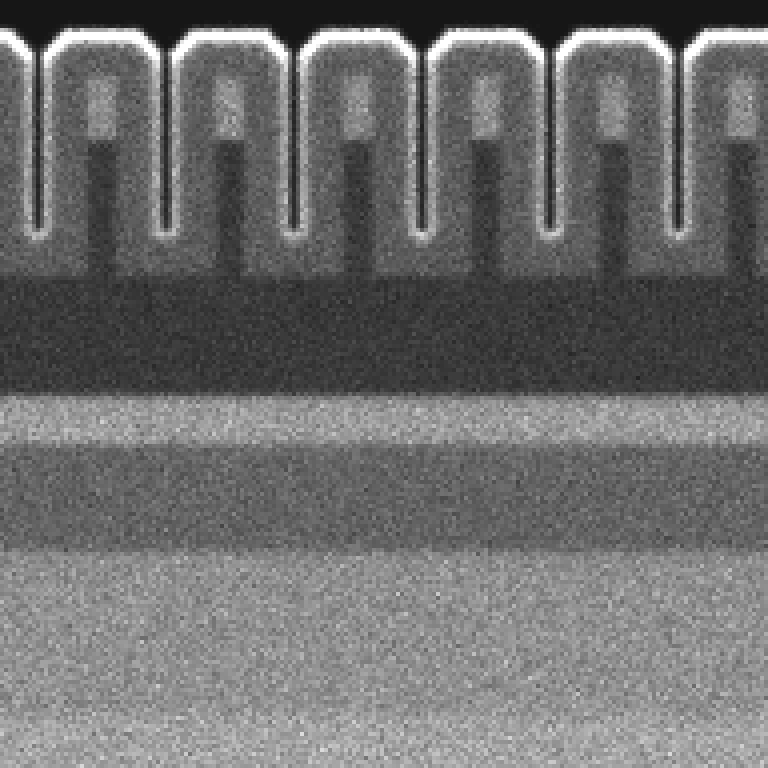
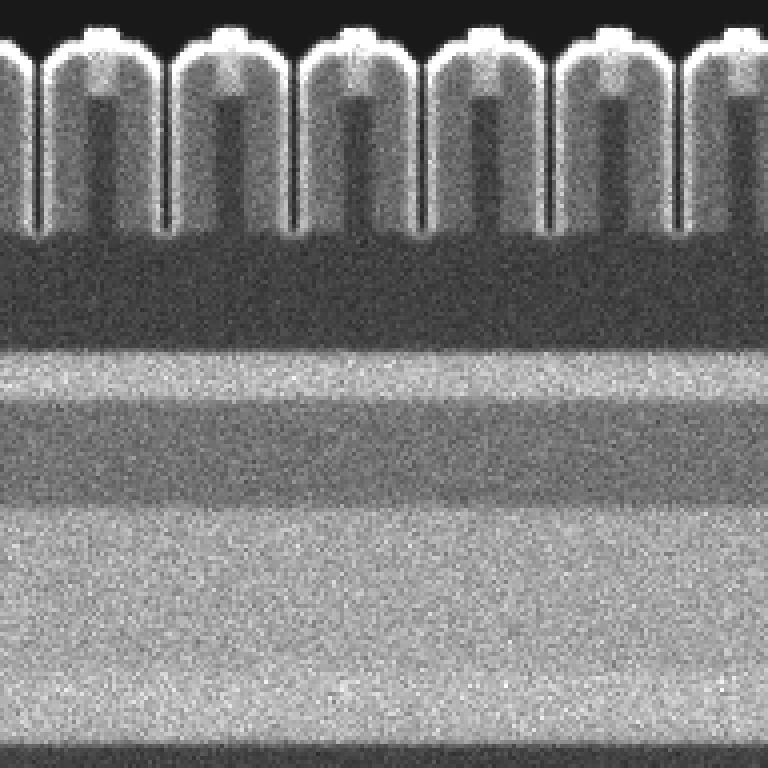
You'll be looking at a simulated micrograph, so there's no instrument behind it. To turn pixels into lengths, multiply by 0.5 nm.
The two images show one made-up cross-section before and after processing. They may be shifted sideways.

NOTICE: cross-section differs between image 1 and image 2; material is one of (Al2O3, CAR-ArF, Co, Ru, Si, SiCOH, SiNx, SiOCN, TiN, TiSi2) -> removed: SiNx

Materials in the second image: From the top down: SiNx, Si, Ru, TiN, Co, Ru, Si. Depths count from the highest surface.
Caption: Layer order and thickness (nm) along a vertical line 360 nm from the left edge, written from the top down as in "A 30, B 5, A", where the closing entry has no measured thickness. empty 6, SiNx 94, Si 60, Ru 24, TiN 54, Co 82, Ru 36, Si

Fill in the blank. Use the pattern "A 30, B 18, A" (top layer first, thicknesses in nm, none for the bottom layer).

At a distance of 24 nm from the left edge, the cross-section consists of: empty 14, SiNx 86, Si 60, Ru 24, TiN 54, Co 82, Ru 36, Si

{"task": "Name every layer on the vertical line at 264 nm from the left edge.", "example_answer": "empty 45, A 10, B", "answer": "empty 10, SiNx 90, Si 60, Ru 24, TiN 54, Co 82, Ru 36, Si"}